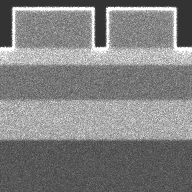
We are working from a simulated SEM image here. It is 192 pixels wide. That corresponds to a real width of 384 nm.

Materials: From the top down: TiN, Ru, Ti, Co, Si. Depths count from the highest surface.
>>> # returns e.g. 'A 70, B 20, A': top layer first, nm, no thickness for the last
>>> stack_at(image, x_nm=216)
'TiN 80, Ru 34, Ti 70, Co 80, Si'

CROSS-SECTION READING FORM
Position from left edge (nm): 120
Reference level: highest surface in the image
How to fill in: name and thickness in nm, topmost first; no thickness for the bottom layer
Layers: TiN 80, Ru 34, Ti 70, Co 80, Si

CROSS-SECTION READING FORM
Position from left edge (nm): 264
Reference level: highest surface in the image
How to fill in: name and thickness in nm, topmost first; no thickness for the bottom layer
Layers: TiN 80, Ru 34, Ti 70, Co 80, Si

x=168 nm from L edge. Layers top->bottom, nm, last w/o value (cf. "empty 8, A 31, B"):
TiN 80, Ru 34, Ti 70, Co 80, Si